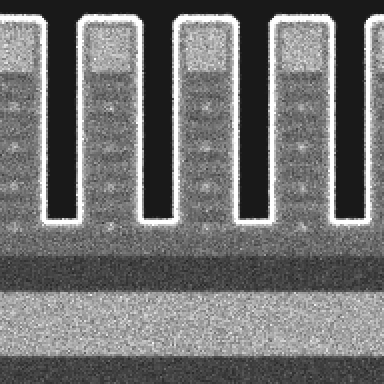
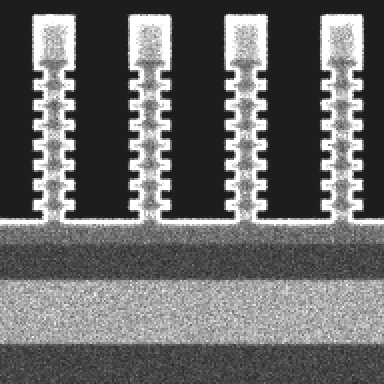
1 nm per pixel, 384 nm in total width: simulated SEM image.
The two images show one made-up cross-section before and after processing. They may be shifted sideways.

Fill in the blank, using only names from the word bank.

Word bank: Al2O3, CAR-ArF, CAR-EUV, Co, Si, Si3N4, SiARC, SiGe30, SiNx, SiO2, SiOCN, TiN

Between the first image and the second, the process removed Si3N4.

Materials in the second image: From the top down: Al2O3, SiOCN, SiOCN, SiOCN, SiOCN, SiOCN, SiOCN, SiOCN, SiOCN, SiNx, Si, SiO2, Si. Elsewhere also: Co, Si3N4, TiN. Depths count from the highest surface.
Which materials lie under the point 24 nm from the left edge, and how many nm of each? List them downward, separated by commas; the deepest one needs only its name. empty 204, SiNx 24, Si 36, SiO2 64, Si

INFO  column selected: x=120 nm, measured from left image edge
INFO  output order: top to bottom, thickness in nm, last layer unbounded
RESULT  empty 204, SiNx 24, Si 36, SiO2 64, Si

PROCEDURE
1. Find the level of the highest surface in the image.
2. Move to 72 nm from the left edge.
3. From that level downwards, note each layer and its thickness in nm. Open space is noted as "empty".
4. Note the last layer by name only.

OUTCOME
Al2O3 44, SiOCN 10, empty 10, SiOCN 10, empty 10, SiOCN 10, empty 10, SiOCN 10, empty 10, SiOCN 10, empty 10, SiOCN 10, empty 10, SiOCN 10, empty 10, SiOCN 10, empty 10, SiNx 24, Si 36, SiO2 64, Si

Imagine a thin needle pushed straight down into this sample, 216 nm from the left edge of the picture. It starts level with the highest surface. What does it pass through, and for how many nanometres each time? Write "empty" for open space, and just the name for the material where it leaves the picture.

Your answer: empty 204, SiNx 24, Si 36, SiO2 64, Si